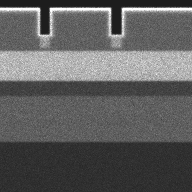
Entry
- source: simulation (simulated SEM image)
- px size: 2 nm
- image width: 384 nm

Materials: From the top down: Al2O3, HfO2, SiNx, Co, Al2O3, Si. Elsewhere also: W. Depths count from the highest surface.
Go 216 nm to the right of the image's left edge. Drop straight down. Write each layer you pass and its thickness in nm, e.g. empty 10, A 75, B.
Al2O3 86, HfO2 60, SiNx 30, Co 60, Al2O3 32, Si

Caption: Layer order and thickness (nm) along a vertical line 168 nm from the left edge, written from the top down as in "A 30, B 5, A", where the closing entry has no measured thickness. Al2O3 86, HfO2 60, SiNx 30, Co 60, Al2O3 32, Si